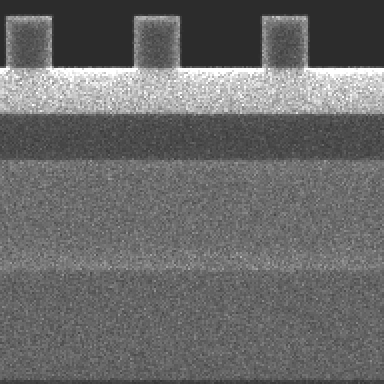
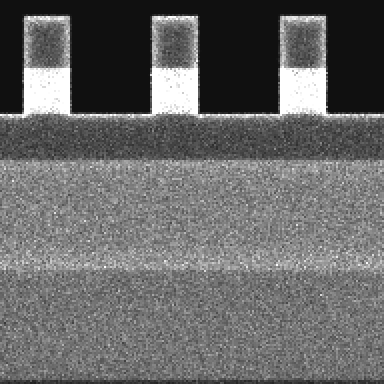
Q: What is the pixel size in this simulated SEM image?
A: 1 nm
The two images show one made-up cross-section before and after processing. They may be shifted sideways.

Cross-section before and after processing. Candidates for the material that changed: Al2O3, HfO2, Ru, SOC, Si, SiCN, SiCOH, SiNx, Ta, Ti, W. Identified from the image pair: HfO2 (removed).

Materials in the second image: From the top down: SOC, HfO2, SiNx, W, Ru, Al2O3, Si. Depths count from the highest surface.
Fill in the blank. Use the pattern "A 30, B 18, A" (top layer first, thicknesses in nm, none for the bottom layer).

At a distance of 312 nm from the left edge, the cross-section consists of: SOC 52, HfO2 46, SiNx 46, W 98, Ru 12, Al2O3 110, Si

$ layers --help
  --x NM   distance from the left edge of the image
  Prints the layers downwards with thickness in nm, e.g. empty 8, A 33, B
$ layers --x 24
SOC 52, HfO2 46, SiNx 46, W 98, Ru 12, Al2O3 110, Si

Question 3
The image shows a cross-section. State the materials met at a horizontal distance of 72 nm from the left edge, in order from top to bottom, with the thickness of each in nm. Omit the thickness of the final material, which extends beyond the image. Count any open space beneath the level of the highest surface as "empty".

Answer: empty 98, SiNx 46, W 98, Ru 12, Al2O3 110, Si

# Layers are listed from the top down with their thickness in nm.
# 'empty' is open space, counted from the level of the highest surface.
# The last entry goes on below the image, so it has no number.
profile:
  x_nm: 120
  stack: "empty 98, SiNx 46, W 98, Ru 12, Al2O3 110, Si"